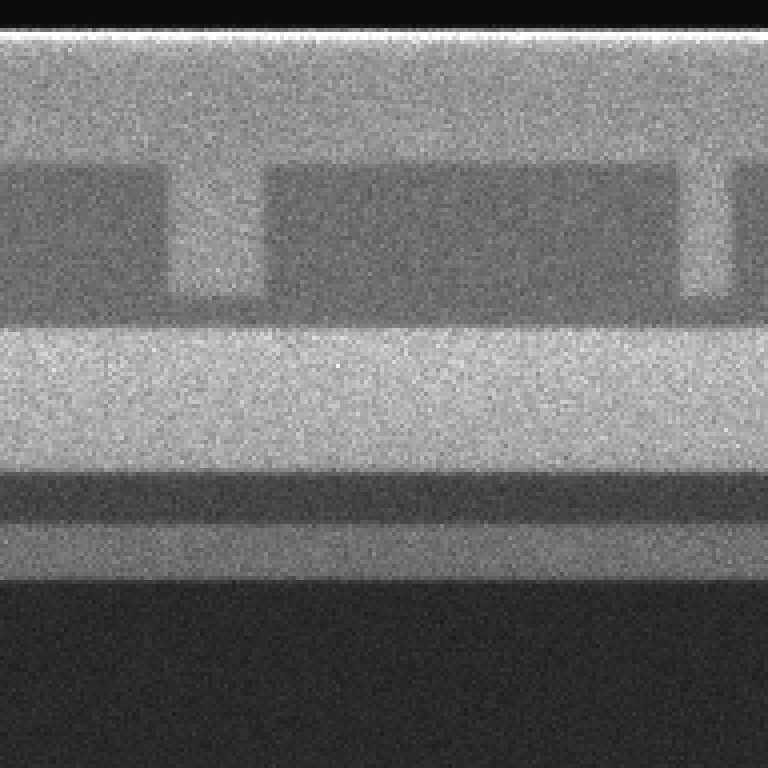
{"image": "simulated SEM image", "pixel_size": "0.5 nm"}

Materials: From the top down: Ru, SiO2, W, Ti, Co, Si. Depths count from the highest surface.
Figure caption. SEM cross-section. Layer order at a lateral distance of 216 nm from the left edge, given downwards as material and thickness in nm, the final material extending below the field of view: Ru 66, SiO2 82, W 72, Ti 26, Co 28, Si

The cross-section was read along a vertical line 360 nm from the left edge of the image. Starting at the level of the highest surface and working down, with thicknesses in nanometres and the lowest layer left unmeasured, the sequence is Ru 132, SiO2 16, W 72, Ti 26, Co 28, Si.